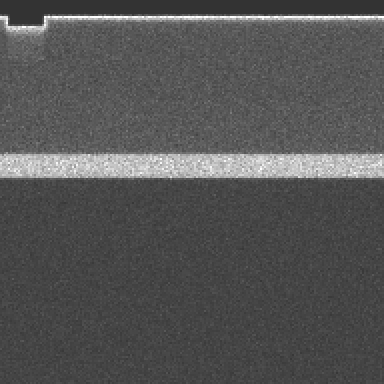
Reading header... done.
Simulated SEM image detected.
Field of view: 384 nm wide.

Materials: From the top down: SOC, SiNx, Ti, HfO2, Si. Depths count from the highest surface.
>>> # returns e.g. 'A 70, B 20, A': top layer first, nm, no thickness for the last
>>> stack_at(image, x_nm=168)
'SiNx 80, Ti 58, HfO2 24, Si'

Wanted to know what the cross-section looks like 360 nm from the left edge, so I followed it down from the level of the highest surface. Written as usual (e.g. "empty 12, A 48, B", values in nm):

SiNx 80, Ti 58, HfO2 24, Si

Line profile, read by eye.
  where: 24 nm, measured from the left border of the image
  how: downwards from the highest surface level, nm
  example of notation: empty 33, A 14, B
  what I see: empty 10, SOC 34, SiNx 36, Ti 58, HfO2 24, Si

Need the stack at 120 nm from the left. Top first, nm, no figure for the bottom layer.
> SiNx 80, Ti 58, HfO2 24, Si